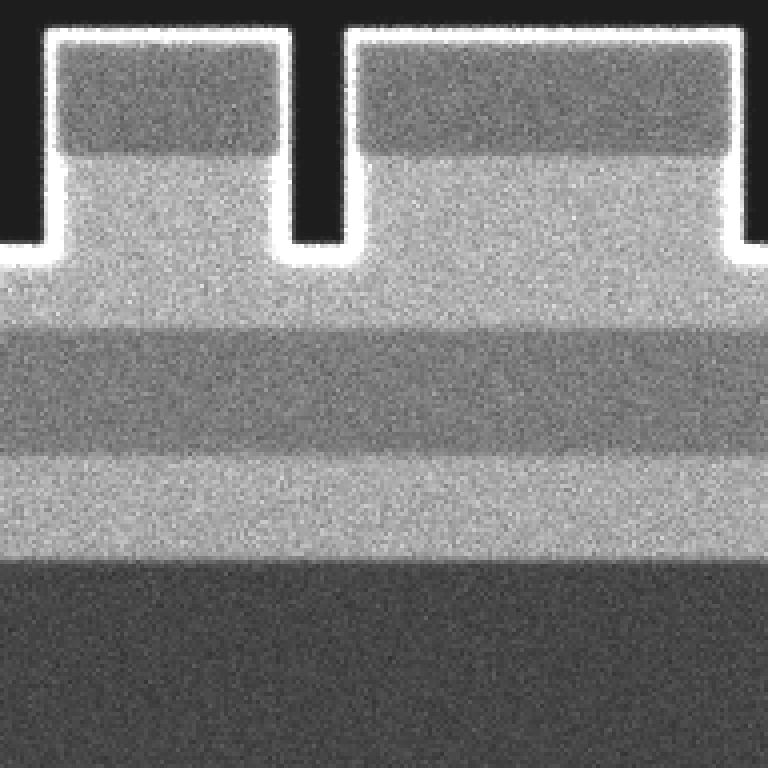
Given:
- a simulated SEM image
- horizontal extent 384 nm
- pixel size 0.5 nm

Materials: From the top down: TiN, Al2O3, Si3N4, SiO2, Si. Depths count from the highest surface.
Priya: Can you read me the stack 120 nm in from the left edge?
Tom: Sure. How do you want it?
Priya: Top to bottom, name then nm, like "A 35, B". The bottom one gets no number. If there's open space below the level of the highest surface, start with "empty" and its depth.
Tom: TiN 62, Al2O3 86, Si3N4 64, SiO2 52, Si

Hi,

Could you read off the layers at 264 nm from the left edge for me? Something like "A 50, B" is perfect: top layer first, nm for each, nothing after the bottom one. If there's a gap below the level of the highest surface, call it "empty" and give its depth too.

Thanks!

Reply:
TiN 62, Al2O3 86, Si3N4 64, SiO2 52, Si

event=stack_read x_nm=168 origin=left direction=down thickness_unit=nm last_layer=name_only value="empty 108, Al2O3 40, Si3N4 64, SiO2 52, Si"